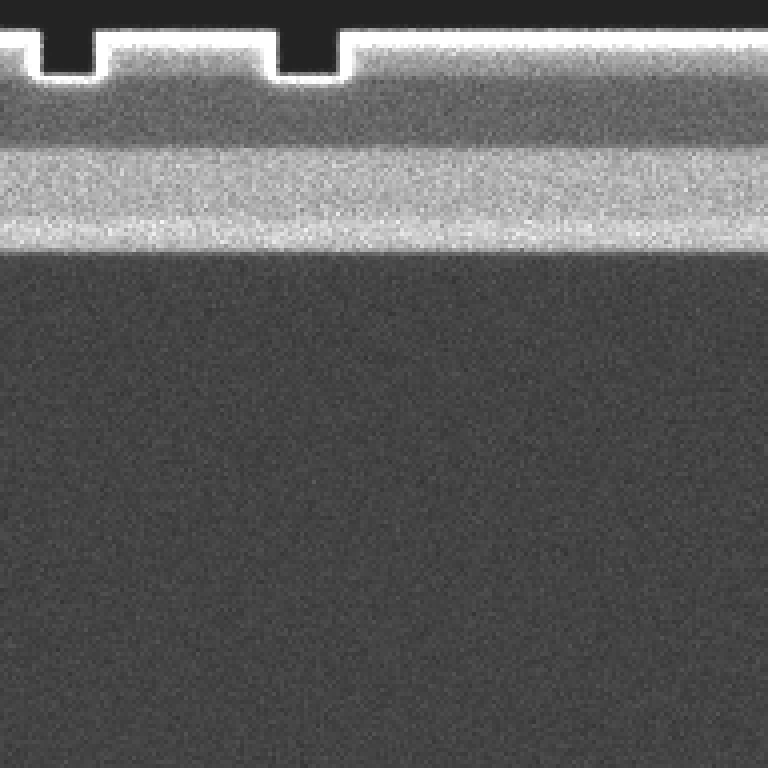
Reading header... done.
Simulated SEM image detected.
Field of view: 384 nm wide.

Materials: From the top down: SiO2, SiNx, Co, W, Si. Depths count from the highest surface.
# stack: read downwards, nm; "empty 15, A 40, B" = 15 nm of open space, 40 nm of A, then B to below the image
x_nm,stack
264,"SiO2 22, SiNx 36, Co 36, W 16, Si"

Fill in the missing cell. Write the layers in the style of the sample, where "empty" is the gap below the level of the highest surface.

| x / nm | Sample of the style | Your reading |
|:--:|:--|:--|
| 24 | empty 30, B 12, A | empty 22, SiNx 36, Co 36, W 16, Si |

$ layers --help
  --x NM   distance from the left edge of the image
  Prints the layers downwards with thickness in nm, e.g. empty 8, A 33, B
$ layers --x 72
SiO2 22, SiNx 36, Co 36, W 16, Si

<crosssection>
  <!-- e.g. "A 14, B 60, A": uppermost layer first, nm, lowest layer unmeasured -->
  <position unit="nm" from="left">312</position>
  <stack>SiO2 22, SiNx 36, Co 36, W 16, Si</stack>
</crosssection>